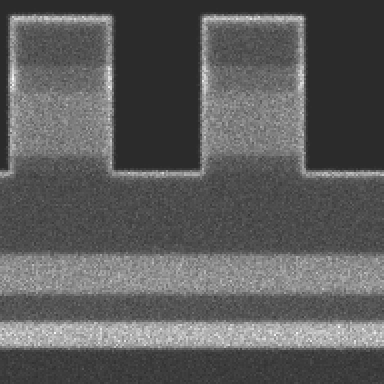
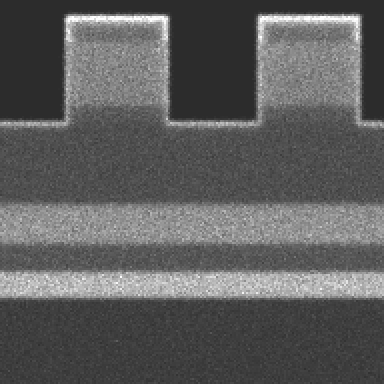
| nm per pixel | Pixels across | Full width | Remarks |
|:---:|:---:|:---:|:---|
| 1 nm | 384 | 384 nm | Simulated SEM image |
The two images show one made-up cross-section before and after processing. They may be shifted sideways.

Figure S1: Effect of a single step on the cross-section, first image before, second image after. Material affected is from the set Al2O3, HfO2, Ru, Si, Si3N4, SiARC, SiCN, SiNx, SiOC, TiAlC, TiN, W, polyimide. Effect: removed SiARC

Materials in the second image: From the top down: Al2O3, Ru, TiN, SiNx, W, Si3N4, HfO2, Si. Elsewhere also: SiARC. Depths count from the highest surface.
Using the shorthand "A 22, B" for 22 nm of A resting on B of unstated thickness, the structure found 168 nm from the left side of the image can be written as empty 106, SiNx 82, W 40, Si3N4 28, HfO2 26, Si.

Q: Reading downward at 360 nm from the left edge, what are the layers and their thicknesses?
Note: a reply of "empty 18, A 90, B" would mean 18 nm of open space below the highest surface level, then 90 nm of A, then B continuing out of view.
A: empty 106, SiNx 82, W 40, Si3N4 28, HfO2 26, Si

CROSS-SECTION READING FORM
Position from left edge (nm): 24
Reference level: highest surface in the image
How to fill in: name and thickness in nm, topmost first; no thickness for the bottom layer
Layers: empty 106, SiNx 82, W 40, Si3N4 28, HfO2 26, Si